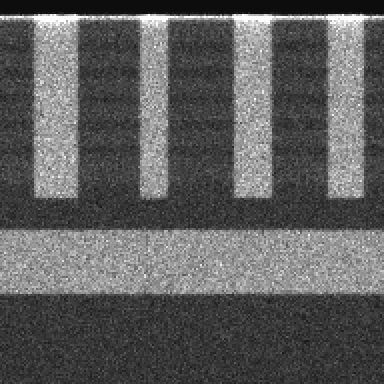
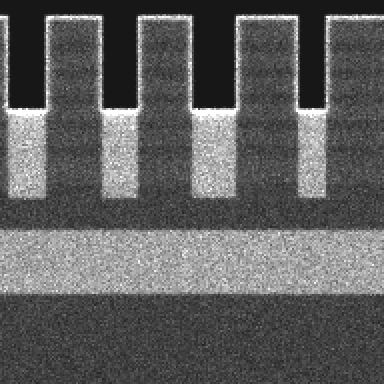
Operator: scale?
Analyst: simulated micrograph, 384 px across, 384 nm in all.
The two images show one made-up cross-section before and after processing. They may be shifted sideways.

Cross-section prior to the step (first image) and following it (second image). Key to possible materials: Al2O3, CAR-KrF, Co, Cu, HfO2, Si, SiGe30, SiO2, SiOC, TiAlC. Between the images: Co was removed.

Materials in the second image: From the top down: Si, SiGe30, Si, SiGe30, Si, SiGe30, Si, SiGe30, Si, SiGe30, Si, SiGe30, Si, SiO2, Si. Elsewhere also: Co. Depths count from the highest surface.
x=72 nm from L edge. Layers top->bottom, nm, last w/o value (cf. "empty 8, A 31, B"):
Si 10, SiGe30 16, Si 10, SiGe30 16, Si 10, SiGe30 16, Si 10, SiGe30 16, Si 10, SiGe30 16, Si 10, SiGe30 28, Si 46, SiO2 64, Si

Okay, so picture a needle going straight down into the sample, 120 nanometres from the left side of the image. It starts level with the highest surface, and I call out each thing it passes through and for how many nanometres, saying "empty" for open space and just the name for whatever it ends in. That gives empty 94, Co 88, Si 32, SiO2 64, Si